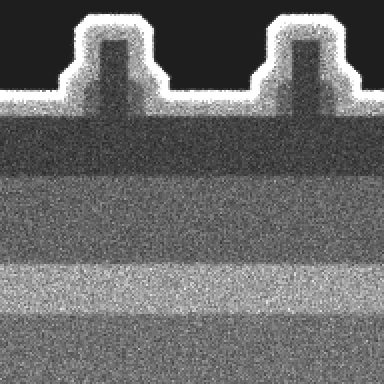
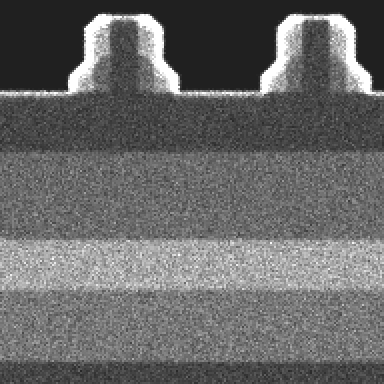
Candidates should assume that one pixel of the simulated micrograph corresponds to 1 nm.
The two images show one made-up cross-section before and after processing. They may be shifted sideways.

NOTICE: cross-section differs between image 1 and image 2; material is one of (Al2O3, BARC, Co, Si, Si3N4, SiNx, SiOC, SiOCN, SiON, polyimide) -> removed: Al2O3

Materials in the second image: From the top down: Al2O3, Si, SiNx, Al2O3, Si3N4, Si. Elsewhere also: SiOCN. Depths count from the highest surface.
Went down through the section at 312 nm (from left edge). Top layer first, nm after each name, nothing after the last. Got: Si 136, SiNx 88, Al2O3 50, Si3N4 72, Si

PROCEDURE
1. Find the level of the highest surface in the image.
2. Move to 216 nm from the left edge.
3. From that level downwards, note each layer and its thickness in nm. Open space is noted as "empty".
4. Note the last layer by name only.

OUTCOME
empty 76, Si 60, SiNx 88, Al2O3 50, Si3N4 72, Si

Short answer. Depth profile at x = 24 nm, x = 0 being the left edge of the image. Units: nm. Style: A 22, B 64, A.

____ empty 76, Si 60, SiNx 88, Al2O3 50, Si3N4 72, Si